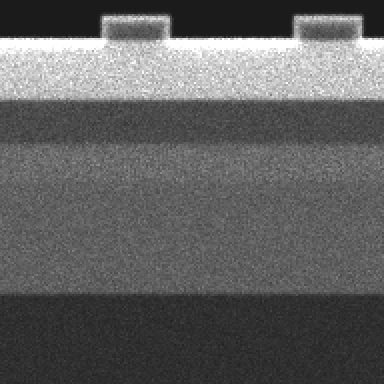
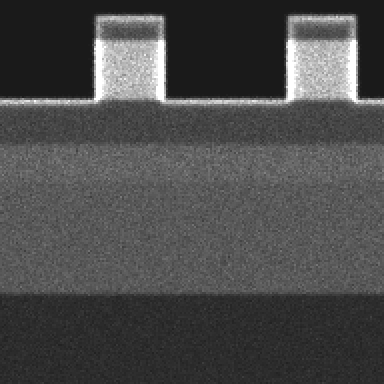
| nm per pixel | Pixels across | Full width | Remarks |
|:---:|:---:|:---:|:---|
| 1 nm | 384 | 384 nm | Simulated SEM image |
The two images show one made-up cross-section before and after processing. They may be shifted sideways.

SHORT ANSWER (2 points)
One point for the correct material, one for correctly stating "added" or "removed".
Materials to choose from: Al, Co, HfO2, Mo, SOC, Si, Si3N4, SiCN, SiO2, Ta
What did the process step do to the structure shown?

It removed HfO2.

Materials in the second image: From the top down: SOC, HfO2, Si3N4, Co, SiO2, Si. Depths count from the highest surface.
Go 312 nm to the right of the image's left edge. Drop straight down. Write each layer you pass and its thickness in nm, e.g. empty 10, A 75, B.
SOC 24, HfO2 60, Si3N4 44, Co 38, SiO2 112, Si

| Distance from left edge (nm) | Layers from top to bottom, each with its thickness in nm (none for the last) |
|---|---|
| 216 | empty 84, Si3N4 44, Co 38, SiO2 112, Si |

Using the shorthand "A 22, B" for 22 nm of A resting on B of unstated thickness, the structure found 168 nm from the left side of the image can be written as empty 84, Si3N4 44, Co 38, SiO2 112, Si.